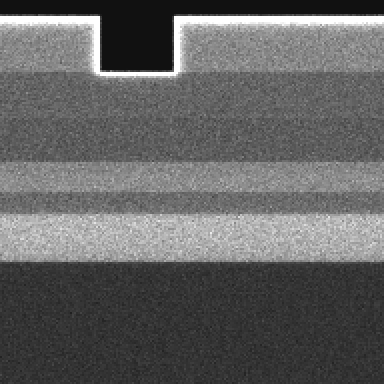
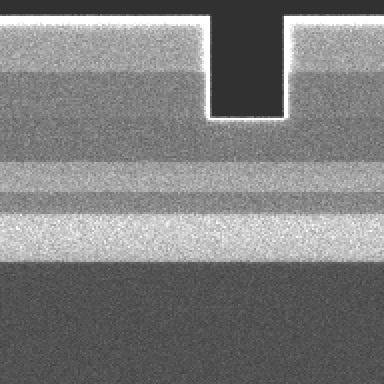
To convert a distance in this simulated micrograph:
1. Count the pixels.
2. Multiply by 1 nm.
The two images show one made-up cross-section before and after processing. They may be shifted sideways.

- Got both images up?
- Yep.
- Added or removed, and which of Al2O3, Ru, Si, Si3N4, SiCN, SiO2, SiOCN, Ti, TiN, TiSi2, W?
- removed, Si3N4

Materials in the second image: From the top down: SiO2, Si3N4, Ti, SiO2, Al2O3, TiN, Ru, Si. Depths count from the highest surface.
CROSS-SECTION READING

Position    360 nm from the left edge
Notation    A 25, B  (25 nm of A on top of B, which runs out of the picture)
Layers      SiO2 56, Si3N4 46, Ti 44, SiO2 12, Al2O3 18, TiN 22, Ru 48, Si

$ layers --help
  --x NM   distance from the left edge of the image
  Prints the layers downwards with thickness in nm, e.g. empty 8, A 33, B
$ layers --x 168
SiO2 56, Si3N4 46, Ti 44, SiO2 12, Al2O3 18, TiN 22, Ru 48, Si